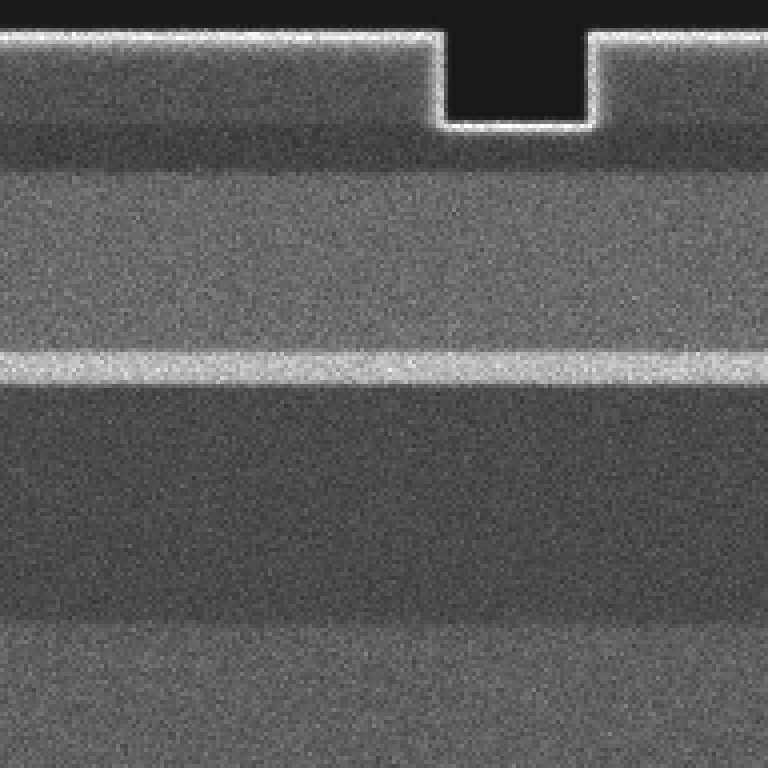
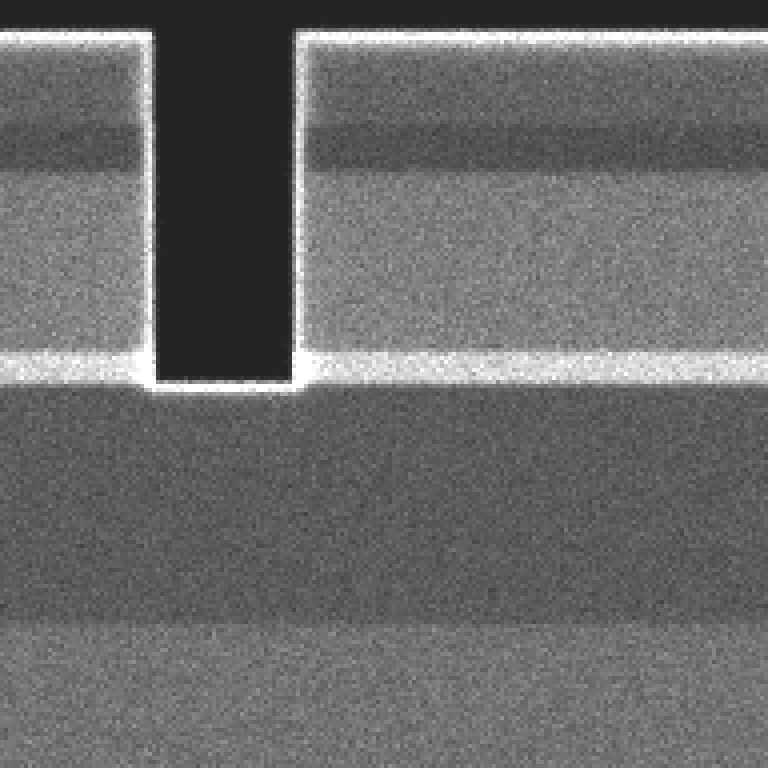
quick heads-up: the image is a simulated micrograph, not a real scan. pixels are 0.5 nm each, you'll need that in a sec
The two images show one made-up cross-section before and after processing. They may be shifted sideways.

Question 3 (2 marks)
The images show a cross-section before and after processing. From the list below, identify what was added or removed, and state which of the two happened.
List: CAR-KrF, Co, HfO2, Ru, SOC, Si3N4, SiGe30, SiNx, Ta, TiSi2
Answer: HfO2 and Ru and SiNx was removed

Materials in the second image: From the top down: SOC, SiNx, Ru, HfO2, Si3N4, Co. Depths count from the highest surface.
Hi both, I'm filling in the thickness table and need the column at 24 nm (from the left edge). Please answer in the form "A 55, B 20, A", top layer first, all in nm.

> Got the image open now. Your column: SOC 46, SiNx 24, Ru 90, HfO2 16, Si3N4 120, Co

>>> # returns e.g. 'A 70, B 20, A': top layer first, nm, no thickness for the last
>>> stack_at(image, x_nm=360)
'SOC 46, SiNx 24, Ru 90, HfO2 16, Si3N4 120, Co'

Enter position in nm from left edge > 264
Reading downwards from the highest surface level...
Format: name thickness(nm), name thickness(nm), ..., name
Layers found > SOC 46, SiNx 24, Ru 90, HfO2 16, Si3N4 120, Co